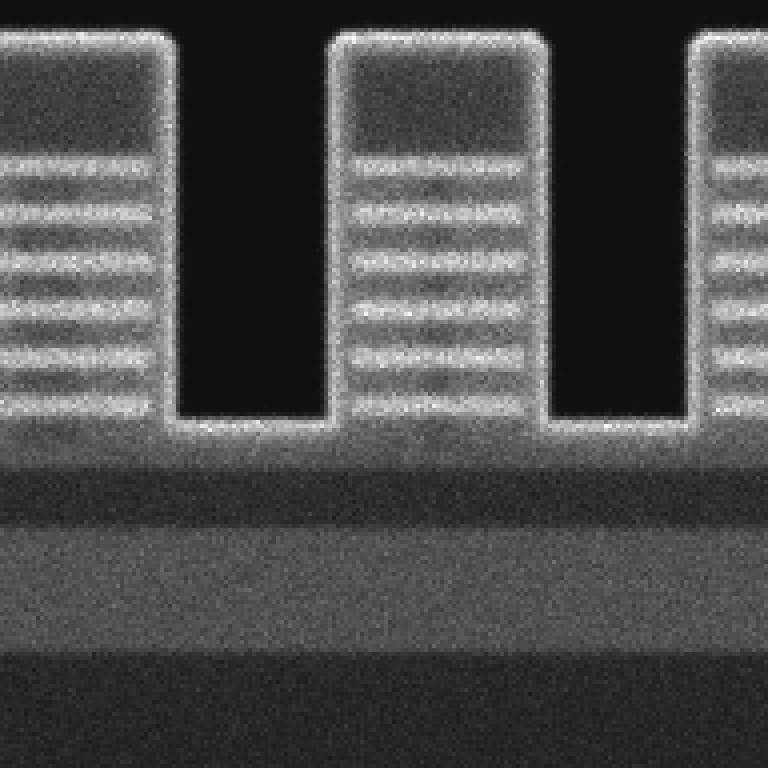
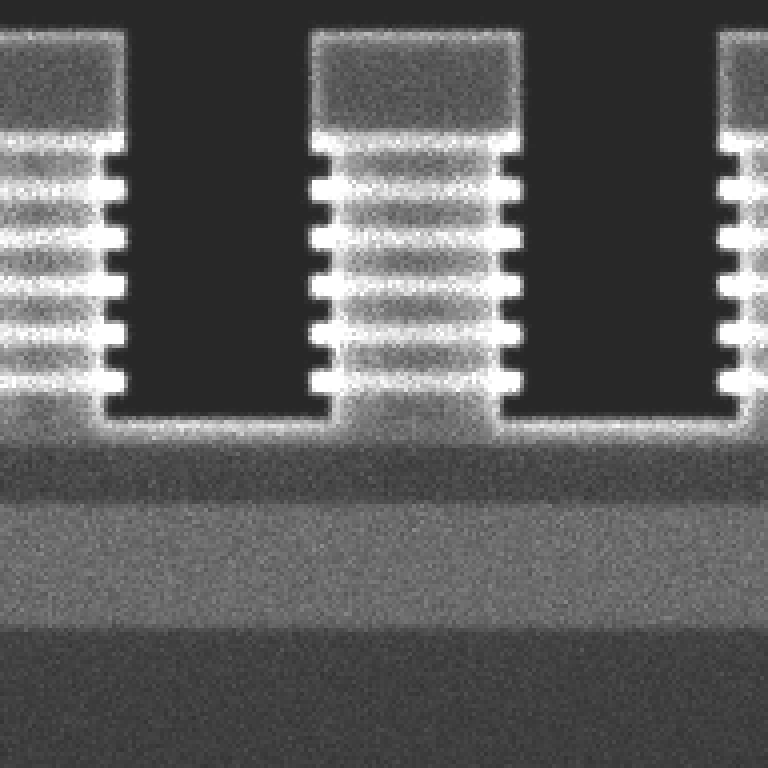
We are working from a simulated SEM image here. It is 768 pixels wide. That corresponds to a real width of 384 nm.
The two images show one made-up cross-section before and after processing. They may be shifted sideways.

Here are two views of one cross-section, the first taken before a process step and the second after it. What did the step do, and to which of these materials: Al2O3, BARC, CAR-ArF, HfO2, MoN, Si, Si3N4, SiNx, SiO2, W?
It removed Al2O3.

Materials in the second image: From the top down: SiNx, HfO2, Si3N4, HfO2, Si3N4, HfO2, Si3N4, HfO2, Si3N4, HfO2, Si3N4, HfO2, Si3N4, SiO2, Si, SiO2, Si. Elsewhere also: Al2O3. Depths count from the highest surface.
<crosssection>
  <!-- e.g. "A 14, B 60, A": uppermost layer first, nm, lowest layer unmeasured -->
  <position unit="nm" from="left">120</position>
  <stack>empty 194, SiO2 12, Si 30, SiO2 62, Si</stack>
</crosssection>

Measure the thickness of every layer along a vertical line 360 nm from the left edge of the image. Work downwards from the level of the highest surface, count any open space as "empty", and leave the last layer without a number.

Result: SiNx 50, HfO2 10, empty 14, HfO2 10, empty 14, HfO2 10, empty 14, HfO2 10, empty 14, HfO2 10, empty 14, HfO2 10, empty 14, SiO2 12, Si 30, SiO2 62, Si